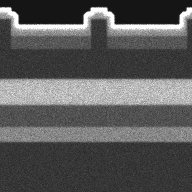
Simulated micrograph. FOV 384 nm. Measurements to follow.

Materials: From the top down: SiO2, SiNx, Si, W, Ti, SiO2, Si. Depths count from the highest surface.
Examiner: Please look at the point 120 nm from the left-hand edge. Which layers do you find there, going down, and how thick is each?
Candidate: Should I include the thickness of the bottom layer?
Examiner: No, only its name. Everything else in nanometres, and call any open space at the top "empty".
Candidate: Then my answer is empty 34, SiO2 22, SiNx 26, Si 60, W 52, Ti 44, SiO2 30, Si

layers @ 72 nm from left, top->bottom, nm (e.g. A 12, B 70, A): empty 34, SiO2 22, SiNx 26, Si 60, W 52, Ti 44, SiO2 30, Si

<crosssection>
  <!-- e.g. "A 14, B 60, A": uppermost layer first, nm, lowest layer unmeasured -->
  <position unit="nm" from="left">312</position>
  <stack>empty 34, SiO2 22, SiNx 26, Si 60, W 52, Ti 44, SiO2 30, Si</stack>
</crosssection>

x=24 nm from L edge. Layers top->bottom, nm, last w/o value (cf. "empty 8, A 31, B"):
empty 8, SiO2 48, SiNx 26, Si 60, W 52, Ti 44, SiO2 30, Si